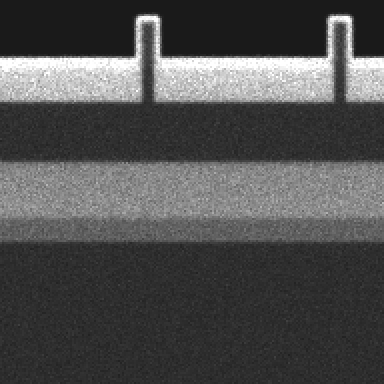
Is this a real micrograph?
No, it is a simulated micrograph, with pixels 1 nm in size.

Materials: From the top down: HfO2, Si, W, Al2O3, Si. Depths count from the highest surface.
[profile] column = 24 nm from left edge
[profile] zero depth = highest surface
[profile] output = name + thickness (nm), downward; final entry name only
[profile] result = empty 42, HfO2 44, Si 60, W 56, Al2O3 24, Si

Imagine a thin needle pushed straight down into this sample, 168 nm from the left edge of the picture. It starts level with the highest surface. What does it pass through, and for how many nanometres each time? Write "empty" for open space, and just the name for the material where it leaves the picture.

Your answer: empty 42, HfO2 44, Si 60, W 56, Al2O3 24, Si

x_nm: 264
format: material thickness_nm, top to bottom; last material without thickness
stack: empty 42, HfO2 44, Si 60, W 56, Al2O3 24, Si